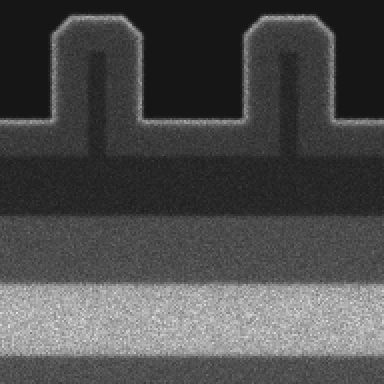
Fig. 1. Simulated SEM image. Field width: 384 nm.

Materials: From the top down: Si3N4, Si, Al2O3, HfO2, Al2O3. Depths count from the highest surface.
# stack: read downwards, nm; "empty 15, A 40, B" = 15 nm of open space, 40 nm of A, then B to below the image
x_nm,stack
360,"empty 104, Si3N4 36, Si 60, Al2O3 68, HfO2 72, Al2O3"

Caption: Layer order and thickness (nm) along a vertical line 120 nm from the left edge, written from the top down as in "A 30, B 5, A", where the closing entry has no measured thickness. Si3N4 140, Si 60, Al2O3 68, HfO2 72, Al2O3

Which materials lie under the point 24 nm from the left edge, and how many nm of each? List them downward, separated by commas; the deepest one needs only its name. empty 104, Si3N4 36, Si 60, Al2O3 68, HfO2 72, Al2O3